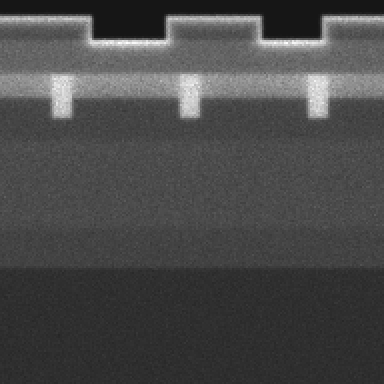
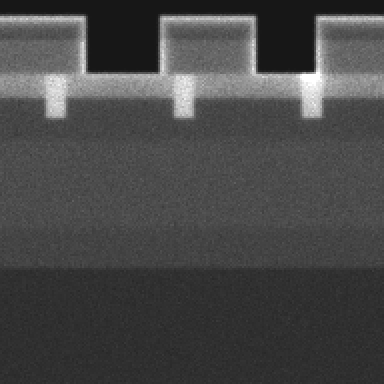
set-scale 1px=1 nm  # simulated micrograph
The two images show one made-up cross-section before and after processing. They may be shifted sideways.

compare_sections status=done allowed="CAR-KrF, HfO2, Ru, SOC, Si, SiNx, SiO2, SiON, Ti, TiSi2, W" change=removed material="SiO2"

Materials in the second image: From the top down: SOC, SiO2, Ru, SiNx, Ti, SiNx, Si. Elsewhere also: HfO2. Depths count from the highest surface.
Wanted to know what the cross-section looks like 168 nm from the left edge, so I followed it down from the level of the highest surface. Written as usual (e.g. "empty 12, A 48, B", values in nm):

SOC 24, SiO2 34, Ru 24, SiNx 42, Ti 88, SiNx 40, Si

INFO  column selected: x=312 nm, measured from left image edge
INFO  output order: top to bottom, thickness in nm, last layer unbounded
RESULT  empty 58, HfO2 44, SiNx 22, Ti 88, SiNx 40, Si